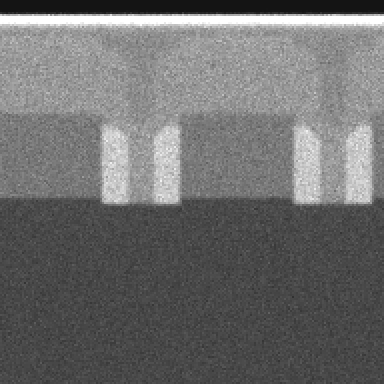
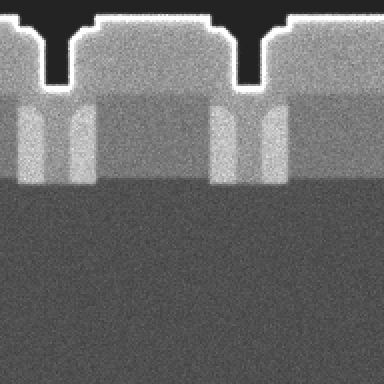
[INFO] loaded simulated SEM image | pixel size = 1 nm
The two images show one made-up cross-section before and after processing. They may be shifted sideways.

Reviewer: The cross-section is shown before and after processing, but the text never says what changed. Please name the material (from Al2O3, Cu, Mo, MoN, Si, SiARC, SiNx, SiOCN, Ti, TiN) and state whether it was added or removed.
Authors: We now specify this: SiARC, removed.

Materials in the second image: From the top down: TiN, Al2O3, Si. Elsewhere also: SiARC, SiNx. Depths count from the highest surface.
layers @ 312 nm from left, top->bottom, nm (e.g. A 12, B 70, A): TiN 78, SiNx 84, Si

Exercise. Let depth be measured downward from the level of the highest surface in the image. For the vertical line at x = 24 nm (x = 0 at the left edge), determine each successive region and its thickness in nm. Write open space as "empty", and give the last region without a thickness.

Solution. empty 12, TiN 78, Al2O3 78, Si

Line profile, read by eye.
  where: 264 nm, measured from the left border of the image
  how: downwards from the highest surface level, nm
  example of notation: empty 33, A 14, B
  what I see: empty 22, TiN 78, Al2O3 68, Si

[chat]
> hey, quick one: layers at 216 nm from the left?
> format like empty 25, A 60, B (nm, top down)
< empty 12, TiN 78, Al2O3 78, Si